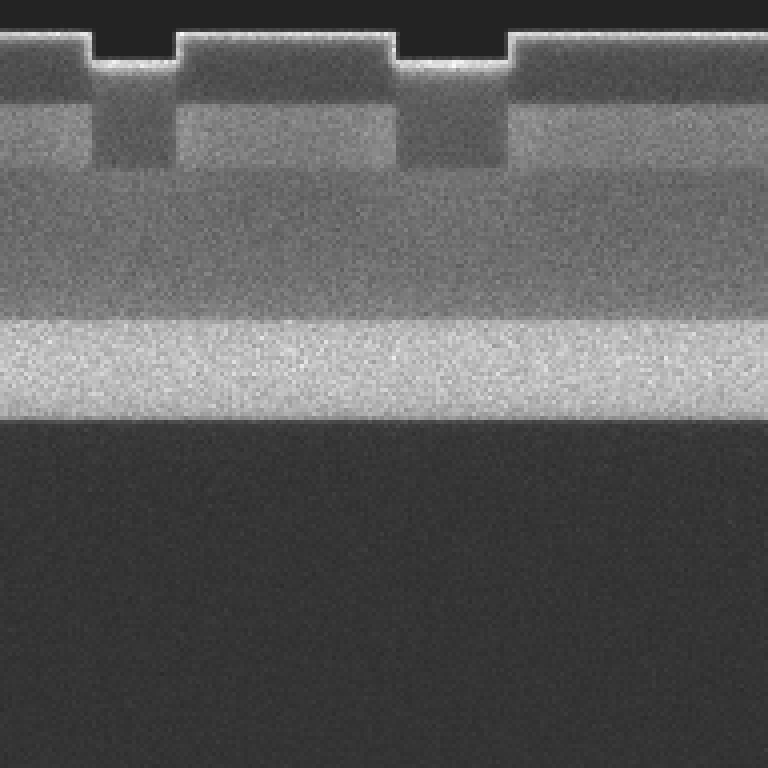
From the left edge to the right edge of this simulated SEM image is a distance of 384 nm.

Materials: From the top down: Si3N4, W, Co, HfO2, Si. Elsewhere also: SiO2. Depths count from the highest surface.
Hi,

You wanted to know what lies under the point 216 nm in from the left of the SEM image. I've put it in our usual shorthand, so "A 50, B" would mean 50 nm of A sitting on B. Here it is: empty 14, SiO2 54, Co 76, HfO2 50, Si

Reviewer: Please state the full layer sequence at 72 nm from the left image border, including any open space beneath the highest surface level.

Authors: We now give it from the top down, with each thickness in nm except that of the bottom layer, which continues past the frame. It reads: empty 14, SiO2 54, Co 76, HfO2 50, Si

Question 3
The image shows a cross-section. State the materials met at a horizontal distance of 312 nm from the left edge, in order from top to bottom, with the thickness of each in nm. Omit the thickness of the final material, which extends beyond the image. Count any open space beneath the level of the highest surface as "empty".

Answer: Si3N4 36, W 32, Co 76, HfO2 50, Si